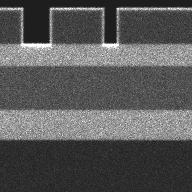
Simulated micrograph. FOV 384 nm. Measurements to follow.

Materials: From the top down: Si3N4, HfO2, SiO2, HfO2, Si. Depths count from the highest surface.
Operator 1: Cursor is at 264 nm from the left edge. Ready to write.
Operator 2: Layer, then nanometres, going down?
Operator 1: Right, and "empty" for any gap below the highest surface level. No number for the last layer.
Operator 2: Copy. Si3N4 72, HfO2 44, SiO2 88, HfO2 60, Si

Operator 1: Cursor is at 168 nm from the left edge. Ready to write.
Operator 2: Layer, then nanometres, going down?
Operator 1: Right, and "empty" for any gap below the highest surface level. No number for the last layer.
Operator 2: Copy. Si3N4 72, HfO2 44, SiO2 88, HfO2 60, Si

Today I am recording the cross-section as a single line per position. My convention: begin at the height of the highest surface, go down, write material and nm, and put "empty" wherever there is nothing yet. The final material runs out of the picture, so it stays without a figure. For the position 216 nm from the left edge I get empty 72, HfO2 44, SiO2 88, HfO2 60, Si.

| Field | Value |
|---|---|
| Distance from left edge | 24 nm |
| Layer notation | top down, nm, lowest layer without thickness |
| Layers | Si3N4 72, HfO2 44, SiO2 88, HfO2 60, Si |